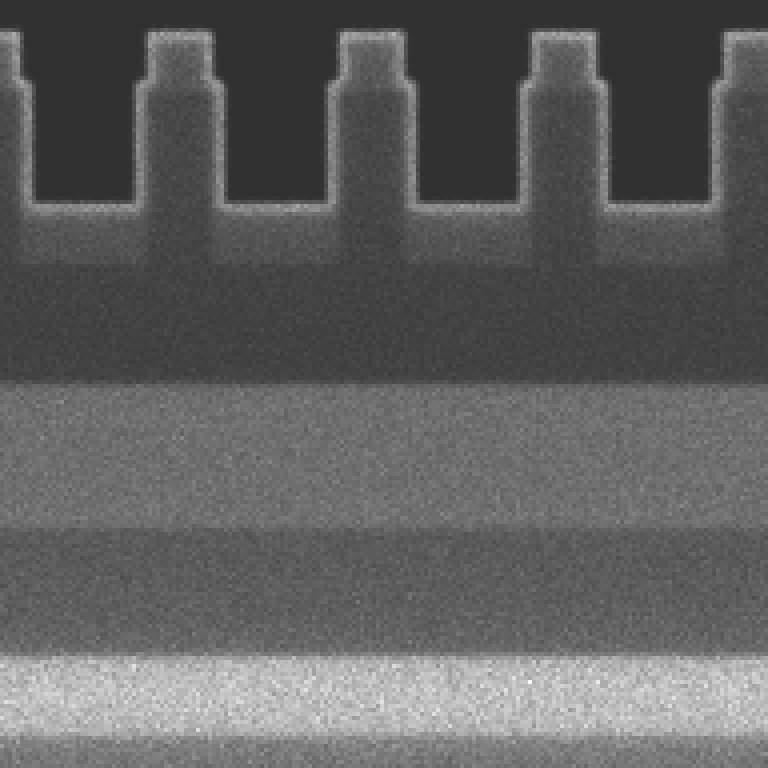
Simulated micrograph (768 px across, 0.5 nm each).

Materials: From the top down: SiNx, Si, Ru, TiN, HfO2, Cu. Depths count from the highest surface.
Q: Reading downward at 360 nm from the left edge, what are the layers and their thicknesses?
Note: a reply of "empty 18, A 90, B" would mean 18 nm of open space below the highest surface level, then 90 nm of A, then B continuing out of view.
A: empty 24, SiNx 92, Si 60, Ru 72, TiN 64, HfO2 40, Cu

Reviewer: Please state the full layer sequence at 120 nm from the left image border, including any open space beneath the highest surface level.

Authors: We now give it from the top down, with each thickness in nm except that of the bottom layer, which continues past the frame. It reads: empty 86, SiNx 30, Si 60, Ru 72, TiN 64, HfO2 40, Cu